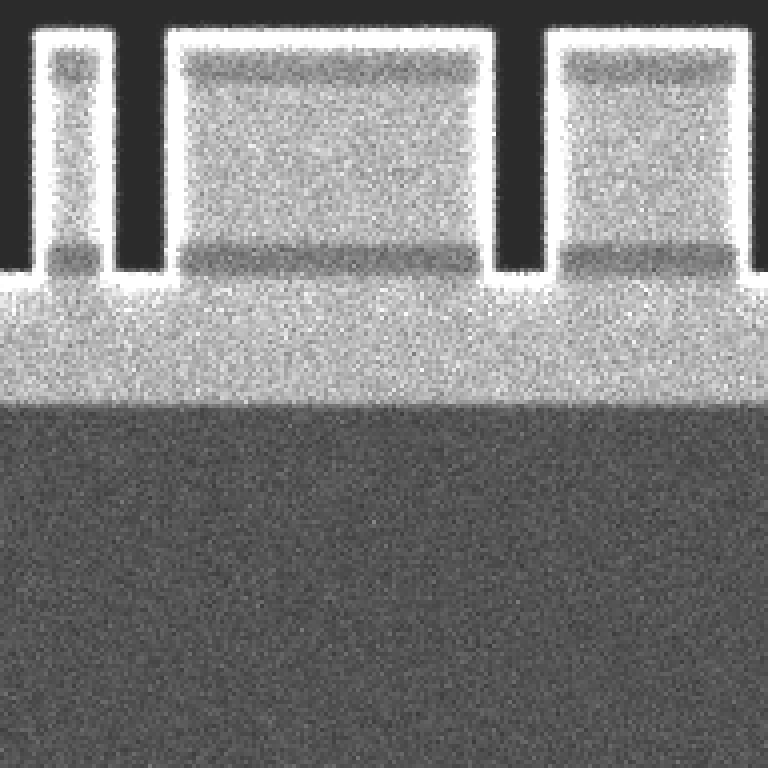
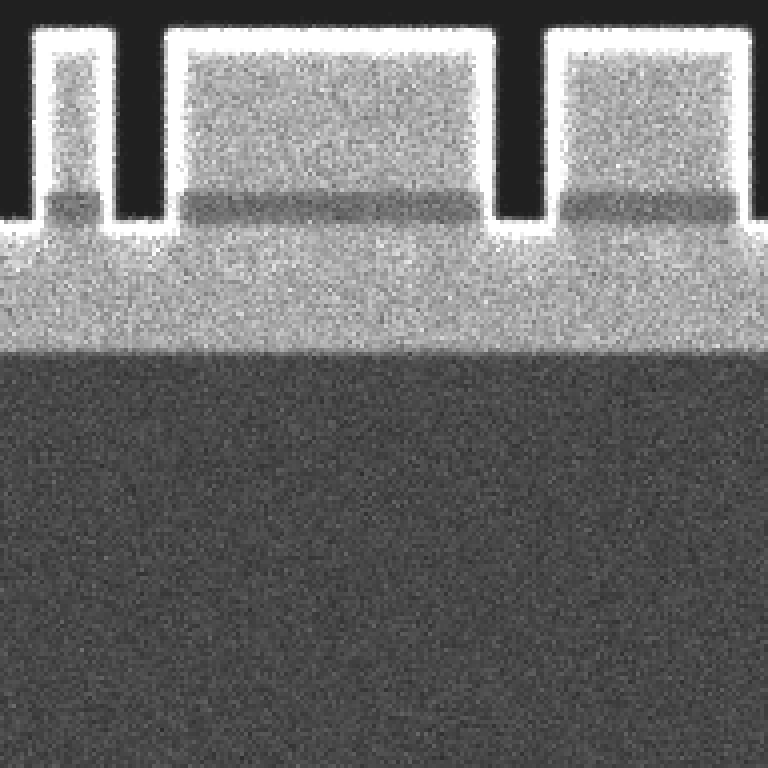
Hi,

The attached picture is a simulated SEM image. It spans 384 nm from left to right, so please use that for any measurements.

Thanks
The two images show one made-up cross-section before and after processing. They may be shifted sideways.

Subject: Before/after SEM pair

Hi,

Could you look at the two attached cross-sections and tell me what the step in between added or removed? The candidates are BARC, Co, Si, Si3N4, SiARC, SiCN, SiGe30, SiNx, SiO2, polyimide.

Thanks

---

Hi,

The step removed SiARC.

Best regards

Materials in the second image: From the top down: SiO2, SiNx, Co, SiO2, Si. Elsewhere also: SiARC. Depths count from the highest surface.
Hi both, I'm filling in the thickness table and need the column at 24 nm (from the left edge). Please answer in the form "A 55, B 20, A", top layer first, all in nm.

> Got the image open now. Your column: SiO2 80, SiNx 16, Co 24, SiO2 40, Si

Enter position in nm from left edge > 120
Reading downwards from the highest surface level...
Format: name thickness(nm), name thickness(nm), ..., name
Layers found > SiO2 80, SiNx 16, Co 24, SiO2 40, Si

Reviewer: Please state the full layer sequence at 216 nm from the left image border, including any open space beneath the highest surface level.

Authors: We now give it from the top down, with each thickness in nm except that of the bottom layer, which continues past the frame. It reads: SiO2 80, SiNx 16, SiO2 64, Si